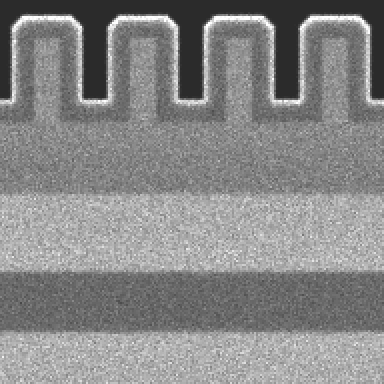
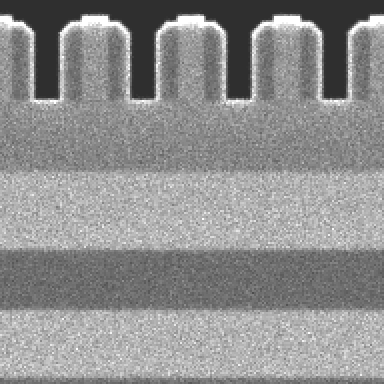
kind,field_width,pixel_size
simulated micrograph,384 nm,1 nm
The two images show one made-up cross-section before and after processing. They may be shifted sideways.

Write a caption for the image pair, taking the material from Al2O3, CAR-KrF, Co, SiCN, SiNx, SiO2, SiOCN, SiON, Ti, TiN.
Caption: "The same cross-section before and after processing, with SiOCN removed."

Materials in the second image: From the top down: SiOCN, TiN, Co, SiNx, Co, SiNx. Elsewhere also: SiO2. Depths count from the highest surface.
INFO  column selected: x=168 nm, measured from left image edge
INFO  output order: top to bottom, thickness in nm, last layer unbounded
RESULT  empty 6, SiOCN 78, TiN 72, Co 78, SiNx 60, Co 68, SiNx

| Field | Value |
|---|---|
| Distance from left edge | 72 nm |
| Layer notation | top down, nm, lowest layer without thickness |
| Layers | empty 6, SiOCN 78, TiN 72, Co 78, SiNx 60, Co 68, SiNx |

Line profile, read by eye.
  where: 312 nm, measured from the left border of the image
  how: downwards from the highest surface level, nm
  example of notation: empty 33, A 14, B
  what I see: empty 8, SiOCN 76, TiN 72, Co 78, SiNx 60, Co 68, SiNx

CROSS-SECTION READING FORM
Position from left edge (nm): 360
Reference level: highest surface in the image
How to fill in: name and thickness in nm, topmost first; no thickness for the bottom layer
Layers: empty 6, SiOCN 78, TiN 72, Co 78, SiNx 60, Co 68, SiNx